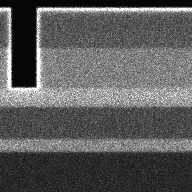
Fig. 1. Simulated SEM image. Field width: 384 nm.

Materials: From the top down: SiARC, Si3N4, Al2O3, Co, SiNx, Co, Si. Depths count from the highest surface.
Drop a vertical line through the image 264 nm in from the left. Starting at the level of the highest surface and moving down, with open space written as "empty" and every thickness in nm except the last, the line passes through SiARC 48, Si3N4 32, Al2O3 80, Co 38, SiNx 64, Co 26, Si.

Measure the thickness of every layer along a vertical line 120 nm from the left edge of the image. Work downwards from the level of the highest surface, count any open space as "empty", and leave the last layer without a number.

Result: SiARC 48, Si3N4 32, Al2O3 80, Co 38, SiNx 64, Co 26, Si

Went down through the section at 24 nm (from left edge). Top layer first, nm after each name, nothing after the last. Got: empty 160, Co 38, SiNx 64, Co 26, Si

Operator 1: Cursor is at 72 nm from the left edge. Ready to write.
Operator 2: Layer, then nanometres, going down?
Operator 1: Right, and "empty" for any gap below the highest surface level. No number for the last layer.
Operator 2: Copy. empty 160, Co 38, SiNx 64, Co 26, Si